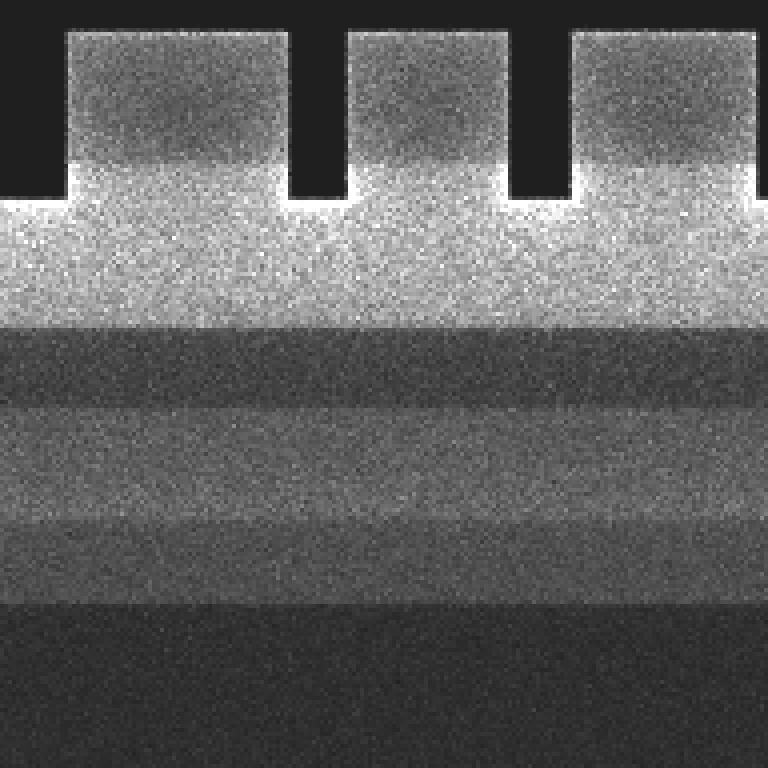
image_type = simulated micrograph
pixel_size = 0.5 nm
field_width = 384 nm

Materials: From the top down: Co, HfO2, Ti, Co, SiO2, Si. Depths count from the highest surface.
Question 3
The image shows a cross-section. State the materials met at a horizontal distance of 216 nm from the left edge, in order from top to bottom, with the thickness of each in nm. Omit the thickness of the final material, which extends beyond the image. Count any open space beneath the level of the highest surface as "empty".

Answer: Co 66, HfO2 82, Ti 40, Co 56, SiO2 42, Si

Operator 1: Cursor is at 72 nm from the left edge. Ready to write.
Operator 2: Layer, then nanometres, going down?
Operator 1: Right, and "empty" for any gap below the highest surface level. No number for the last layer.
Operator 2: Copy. Co 66, HfO2 82, Ti 40, Co 56, SiO2 42, Si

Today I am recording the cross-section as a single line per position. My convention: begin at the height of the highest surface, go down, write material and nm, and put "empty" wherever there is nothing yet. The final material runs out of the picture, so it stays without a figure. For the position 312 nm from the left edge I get Co 66, HfO2 82, Ti 40, Co 56, SiO2 42, Si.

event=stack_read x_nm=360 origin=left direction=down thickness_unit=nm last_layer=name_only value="Co 66, HfO2 82, Ti 40, Co 56, SiO2 42, Si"